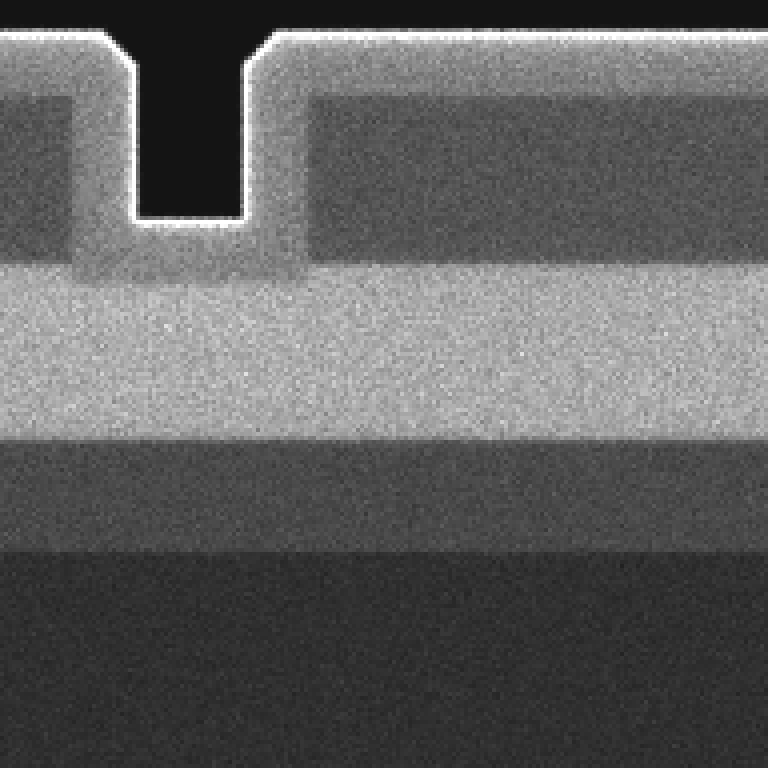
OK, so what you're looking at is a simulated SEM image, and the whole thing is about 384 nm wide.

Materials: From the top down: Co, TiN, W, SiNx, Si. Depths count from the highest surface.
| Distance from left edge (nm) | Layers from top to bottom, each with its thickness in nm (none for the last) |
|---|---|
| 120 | empty 94, Co 32, W 78, SiNx 56, Si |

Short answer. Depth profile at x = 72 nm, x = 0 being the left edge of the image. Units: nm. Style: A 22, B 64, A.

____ empty 94, Co 32, W 78, SiNx 56, Si